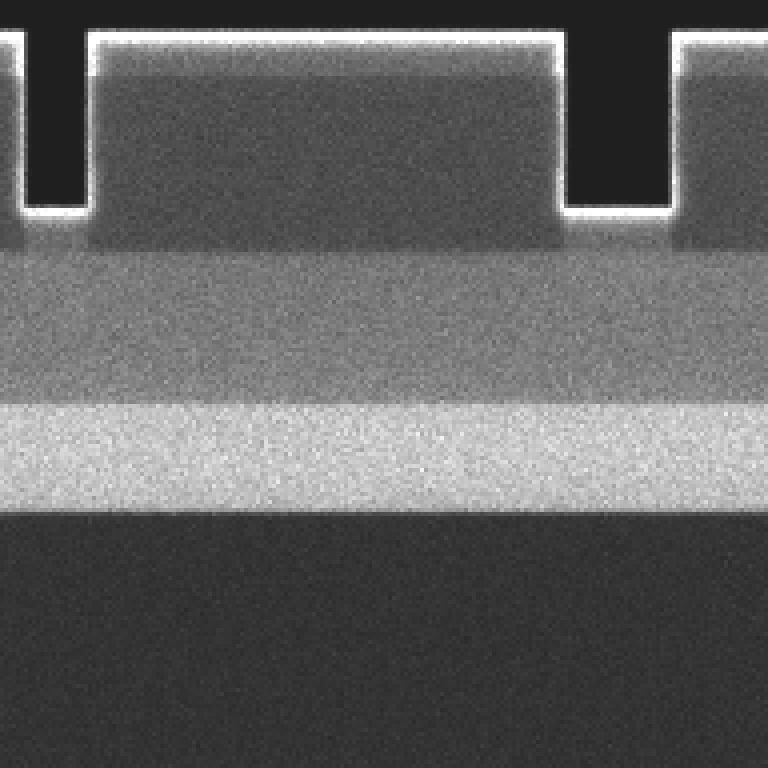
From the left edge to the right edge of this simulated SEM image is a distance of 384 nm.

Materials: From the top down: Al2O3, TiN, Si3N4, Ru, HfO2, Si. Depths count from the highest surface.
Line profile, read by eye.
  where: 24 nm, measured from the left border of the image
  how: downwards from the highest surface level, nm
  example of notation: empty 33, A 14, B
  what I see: empty 88, Al2O3 22, Ru 76, HfO2 54, Si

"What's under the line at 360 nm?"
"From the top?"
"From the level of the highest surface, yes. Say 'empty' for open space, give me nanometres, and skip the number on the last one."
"Al2O3 22, TiN 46, Si3N4 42, Ru 76, HfO2 54, Si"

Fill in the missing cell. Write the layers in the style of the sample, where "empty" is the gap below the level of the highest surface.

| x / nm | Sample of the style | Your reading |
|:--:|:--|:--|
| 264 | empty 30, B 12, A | Al2O3 22, TiN 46, Si3N4 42, Ru 76, HfO2 54, Si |